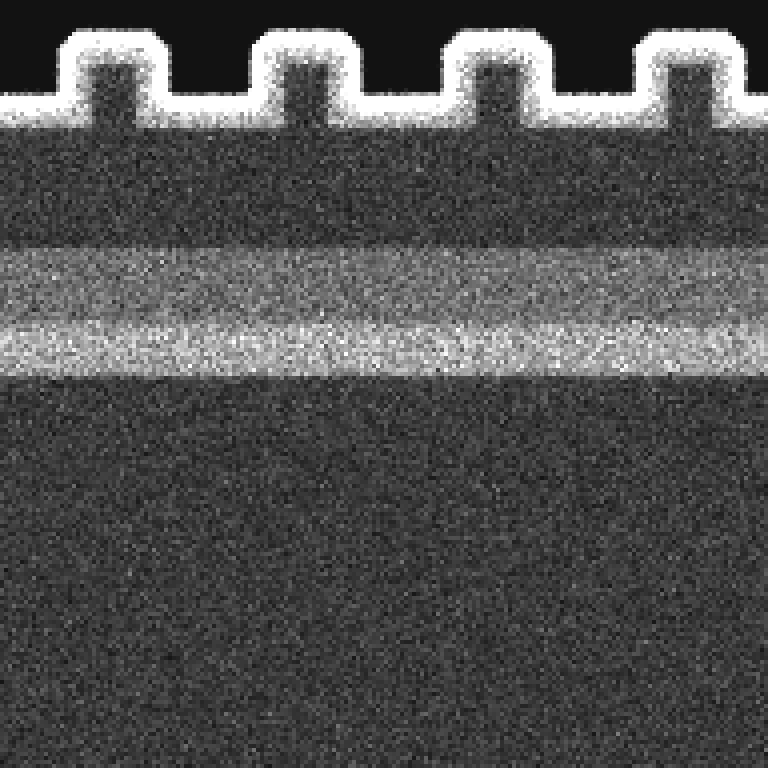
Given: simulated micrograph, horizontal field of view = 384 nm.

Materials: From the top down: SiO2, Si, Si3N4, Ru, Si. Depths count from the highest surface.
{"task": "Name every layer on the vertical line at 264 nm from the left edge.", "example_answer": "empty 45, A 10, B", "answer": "SiO2 48, Si 60, Si3N4 38, Ru 26, Si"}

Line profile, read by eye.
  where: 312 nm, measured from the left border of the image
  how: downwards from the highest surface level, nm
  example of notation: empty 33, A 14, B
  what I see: empty 32, SiO2 16, Si 60, Si3N4 38, Ru 26, Si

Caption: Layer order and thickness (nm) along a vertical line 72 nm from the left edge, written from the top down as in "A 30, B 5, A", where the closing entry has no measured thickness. SiO2 48, Si 60, Si3N4 38, Ru 26, Si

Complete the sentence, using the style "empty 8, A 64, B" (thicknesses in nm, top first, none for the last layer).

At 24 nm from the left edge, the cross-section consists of empty 32, SiO2 16, Si 60, Si3N4 38, Ru 26, Si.